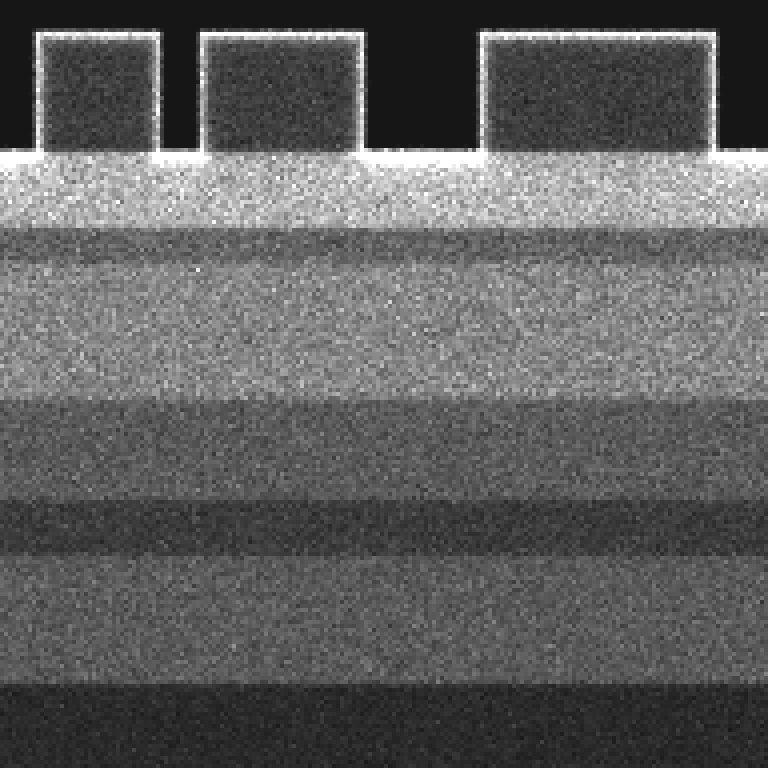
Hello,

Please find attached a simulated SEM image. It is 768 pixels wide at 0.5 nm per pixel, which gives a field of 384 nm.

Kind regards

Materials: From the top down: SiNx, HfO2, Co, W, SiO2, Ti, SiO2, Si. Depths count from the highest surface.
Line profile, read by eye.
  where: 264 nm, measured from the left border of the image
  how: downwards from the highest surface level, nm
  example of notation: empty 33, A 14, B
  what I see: SiNx 60, HfO2 38, Co 18, W 68, SiO2 50, Ti 28, SiO2 64, Si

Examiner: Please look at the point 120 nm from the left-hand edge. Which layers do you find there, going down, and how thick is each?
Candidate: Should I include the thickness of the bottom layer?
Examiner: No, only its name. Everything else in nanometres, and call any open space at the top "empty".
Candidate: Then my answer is SiNx 60, HfO2 38, Co 18, W 68, SiO2 50, Ti 28, SiO2 64, Si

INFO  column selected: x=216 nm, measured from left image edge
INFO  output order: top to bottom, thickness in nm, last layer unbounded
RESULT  empty 60, HfO2 38, Co 18, W 68, SiO2 50, Ti 28, SiO2 64, Si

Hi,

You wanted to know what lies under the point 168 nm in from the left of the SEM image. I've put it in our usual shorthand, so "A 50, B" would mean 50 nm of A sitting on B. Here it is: SiNx 60, HfO2 38, Co 18, W 68, SiO2 50, Ti 28, SiO2 64, Si